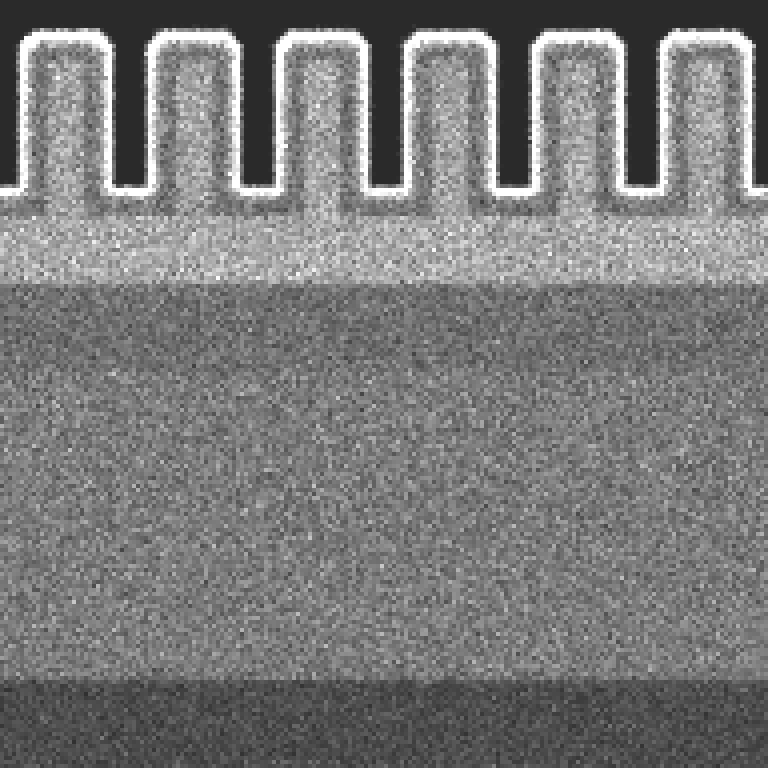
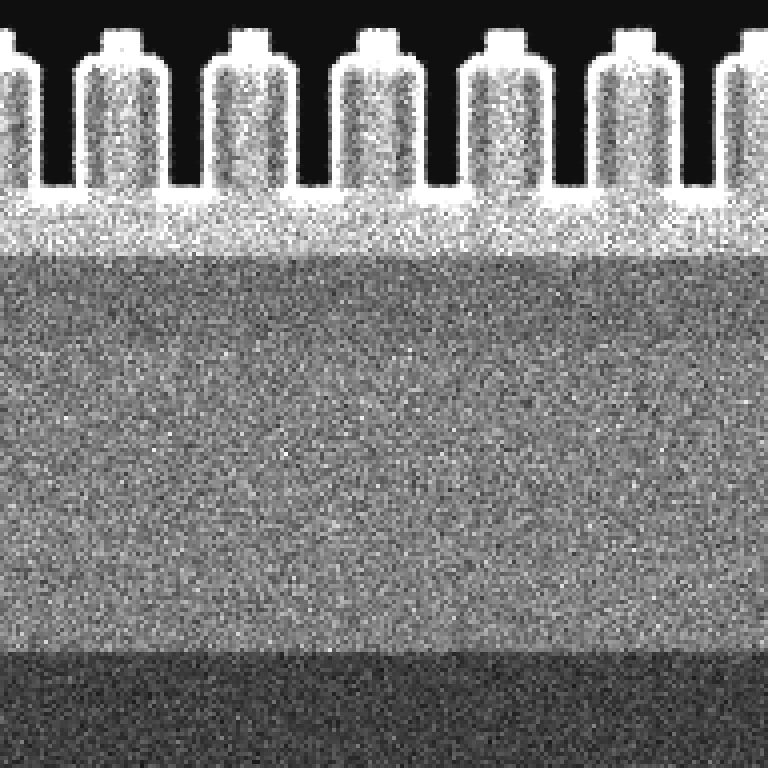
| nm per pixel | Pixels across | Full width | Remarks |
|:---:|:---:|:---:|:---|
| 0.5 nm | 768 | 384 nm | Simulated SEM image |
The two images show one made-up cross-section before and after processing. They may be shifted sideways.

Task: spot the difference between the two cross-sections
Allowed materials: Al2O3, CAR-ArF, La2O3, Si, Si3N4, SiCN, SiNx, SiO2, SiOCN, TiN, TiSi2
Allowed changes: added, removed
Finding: removed SiOCN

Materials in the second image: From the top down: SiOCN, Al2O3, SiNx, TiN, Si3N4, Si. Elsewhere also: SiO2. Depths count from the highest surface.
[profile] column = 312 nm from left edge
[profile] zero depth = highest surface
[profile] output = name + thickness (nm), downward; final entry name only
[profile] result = SiO2 78, Al2O3 34, SiNx 44, TiN 84, Si3N4 70, Si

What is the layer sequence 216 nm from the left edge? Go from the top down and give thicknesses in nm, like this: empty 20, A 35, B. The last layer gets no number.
empty 78, Al2O3 34, SiNx 44, TiN 84, Si3N4 70, Si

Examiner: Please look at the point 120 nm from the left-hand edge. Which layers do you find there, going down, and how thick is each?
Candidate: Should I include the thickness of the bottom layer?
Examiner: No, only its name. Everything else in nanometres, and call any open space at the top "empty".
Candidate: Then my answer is SiO2 78, Al2O3 34, SiNx 44, TiN 84, Si3N4 70, Si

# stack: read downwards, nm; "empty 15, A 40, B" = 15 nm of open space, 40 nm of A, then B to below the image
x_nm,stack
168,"empty 16, SiOCN 62, Al2O3 34, SiNx 44, TiN 84, Si3N4 70, Si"